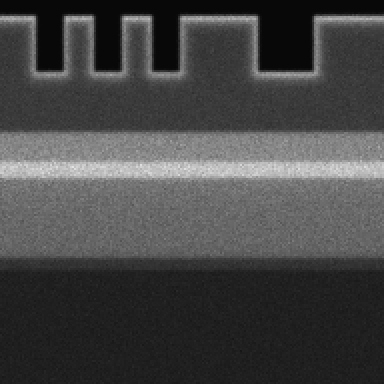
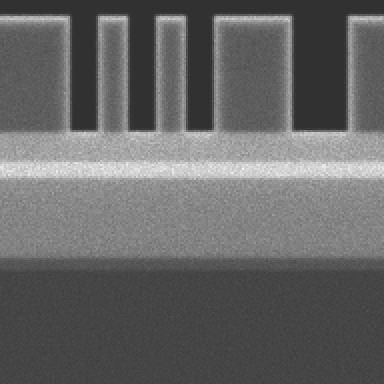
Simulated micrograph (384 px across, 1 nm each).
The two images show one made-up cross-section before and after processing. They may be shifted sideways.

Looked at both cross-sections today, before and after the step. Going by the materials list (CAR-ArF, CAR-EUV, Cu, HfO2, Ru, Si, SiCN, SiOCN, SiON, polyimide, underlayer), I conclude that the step removed underlayer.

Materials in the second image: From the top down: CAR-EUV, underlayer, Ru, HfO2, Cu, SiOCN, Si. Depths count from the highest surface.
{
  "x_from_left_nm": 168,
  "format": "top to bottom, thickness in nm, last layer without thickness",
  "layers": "CAR-EUV 56, underlayer 60, Ru 30, HfO2 16, Cu 80, SiOCN 12, Si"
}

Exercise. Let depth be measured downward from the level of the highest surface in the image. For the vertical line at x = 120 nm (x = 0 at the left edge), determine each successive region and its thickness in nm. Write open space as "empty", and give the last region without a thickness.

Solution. CAR-EUV 56, underlayer 60, Ru 30, HfO2 16, Cu 80, SiOCN 12, Si